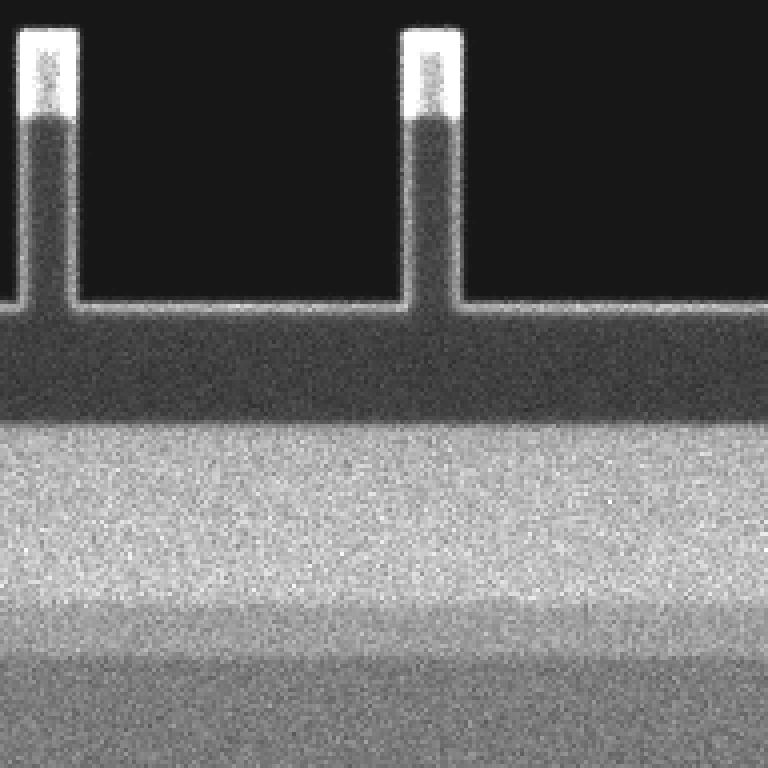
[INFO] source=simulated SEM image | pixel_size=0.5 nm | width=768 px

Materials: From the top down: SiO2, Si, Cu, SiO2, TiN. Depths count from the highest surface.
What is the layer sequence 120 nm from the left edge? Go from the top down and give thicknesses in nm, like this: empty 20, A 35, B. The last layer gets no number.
empty 136, Si 60, Cu 90, SiO2 26, TiN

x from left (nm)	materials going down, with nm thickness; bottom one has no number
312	empty 136, Si 60, Cu 90, SiO2 26, TiN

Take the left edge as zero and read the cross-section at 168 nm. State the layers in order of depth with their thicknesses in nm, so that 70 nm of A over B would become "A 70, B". empty 136, Si 60, Cu 90, SiO2 26, TiN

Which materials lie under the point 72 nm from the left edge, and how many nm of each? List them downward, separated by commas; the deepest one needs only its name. empty 136, Si 60, Cu 90, SiO2 26, TiN